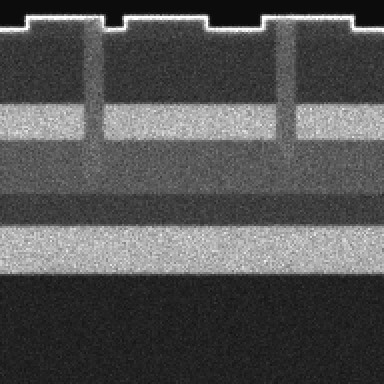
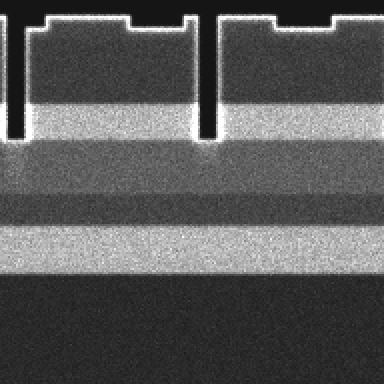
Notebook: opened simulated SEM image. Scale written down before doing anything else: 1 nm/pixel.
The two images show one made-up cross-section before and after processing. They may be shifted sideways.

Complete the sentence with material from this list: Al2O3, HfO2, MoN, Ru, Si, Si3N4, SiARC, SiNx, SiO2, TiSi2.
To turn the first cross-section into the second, Ru must be removed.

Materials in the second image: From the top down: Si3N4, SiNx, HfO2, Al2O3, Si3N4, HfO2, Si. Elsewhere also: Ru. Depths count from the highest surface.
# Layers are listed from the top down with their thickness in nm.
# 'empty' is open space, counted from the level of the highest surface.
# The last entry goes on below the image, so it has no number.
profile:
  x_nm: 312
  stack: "empty 12, Si3N4 12, SiNx 64, HfO2 36, Al2O3 54, Si3N4 32, HfO2 48, Si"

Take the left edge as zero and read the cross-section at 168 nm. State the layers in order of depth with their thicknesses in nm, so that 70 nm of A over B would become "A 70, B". empty 12, Si3N4 12, SiNx 64, HfO2 36, Al2O3 54, Si3N4 32, HfO2 48, Si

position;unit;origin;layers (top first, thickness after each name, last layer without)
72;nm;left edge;Si3N4 24, SiNx 64, HfO2 36, Al2O3 54, Si3N4 32, HfO2 48, Si